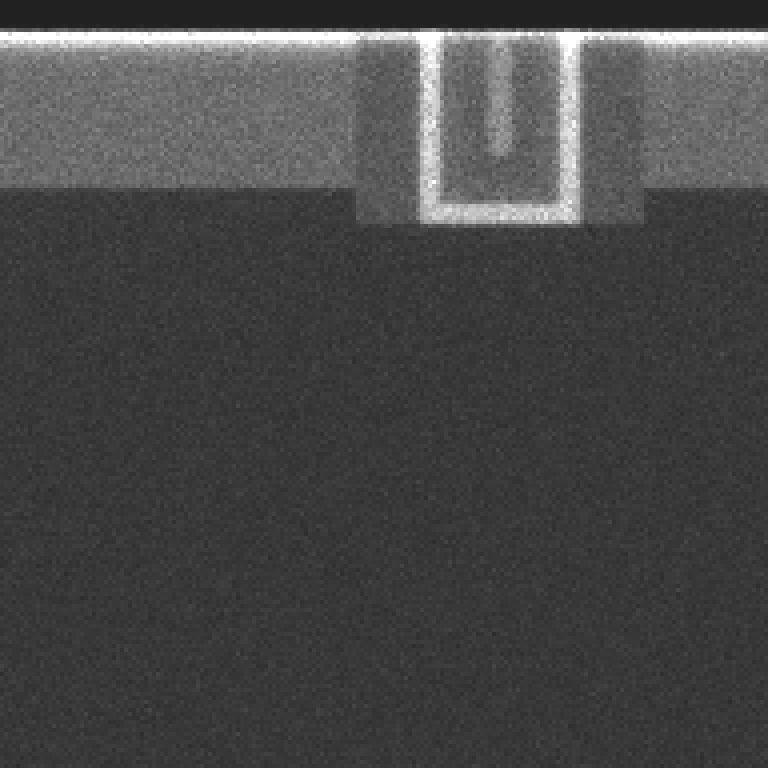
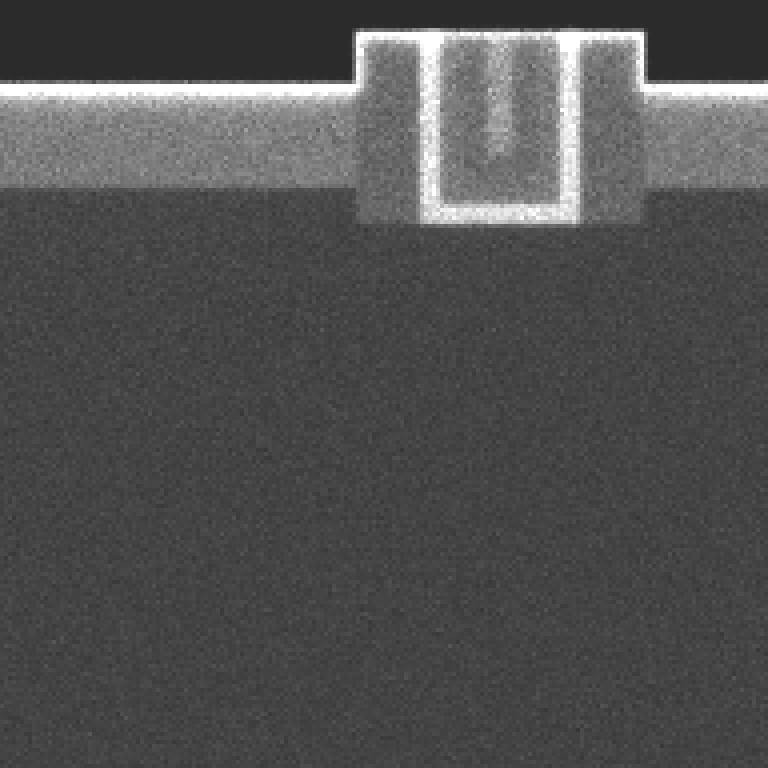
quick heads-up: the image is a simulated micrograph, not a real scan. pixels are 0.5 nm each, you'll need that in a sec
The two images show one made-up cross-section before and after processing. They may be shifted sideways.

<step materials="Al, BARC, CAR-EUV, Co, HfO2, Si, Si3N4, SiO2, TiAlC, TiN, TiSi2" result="removed SiO2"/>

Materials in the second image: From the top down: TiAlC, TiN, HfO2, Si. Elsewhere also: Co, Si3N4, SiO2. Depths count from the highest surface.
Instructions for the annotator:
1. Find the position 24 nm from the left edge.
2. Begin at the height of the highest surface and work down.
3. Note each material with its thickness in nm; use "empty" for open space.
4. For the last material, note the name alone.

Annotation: empty 26, SiO2 52, Si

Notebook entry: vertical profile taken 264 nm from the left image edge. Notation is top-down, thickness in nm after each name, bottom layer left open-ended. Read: TiAlC 74, TiN 12, HfO2 10, Si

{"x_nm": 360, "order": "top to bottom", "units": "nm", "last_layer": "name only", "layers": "empty 26, SiO2 52, Si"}